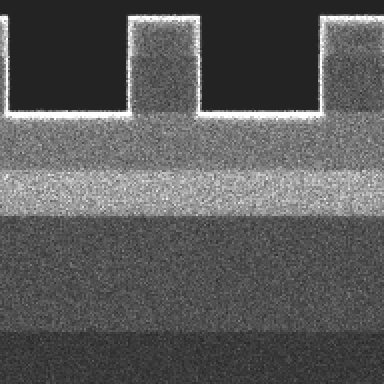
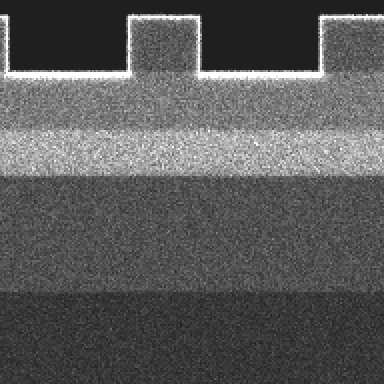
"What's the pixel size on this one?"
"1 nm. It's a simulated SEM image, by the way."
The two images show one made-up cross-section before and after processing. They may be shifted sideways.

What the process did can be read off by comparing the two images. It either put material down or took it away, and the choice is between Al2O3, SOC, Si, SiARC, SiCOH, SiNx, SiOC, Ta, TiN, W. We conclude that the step removed SOC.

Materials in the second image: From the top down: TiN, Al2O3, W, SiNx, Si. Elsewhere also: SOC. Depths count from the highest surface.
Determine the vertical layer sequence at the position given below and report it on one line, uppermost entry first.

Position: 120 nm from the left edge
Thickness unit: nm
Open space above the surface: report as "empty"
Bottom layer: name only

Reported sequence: empty 56, Al2O3 58, W 46, SiNx 116, Si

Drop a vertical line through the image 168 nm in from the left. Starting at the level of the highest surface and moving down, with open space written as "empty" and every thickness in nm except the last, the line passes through TiN 56, Al2O3 58, W 46, SiNx 116, Si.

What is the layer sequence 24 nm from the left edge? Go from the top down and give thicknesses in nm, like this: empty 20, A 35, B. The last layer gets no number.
empty 56, Al2O3 58, W 46, SiNx 116, Si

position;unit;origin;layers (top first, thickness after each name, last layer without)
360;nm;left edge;TiN 56, Al2O3 58, W 46, SiNx 116, Si